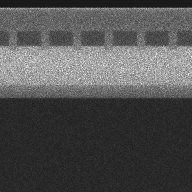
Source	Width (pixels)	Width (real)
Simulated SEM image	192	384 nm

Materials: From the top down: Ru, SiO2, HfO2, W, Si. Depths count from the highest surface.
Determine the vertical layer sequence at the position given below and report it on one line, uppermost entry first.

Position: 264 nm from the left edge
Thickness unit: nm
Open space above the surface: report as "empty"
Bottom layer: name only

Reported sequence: Ru 46, SiO2 30, HfO2 78, W 26, Si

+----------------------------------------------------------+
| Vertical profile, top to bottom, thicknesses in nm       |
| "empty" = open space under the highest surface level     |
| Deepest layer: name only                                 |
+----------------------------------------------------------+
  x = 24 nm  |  Ru 84, HfO2 70, W 26, Si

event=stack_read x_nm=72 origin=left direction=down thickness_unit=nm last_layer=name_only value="Ru 46, SiO2 30, HfO2 78, W 26, Si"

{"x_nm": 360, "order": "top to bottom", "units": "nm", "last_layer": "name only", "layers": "Ru 46, SiO2 30, HfO2 78, W 26, Si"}